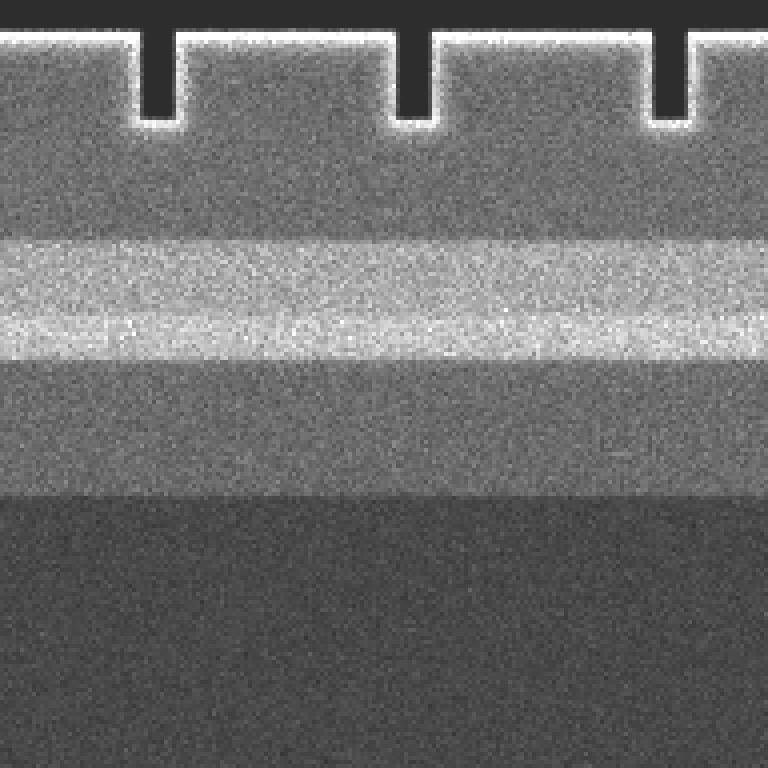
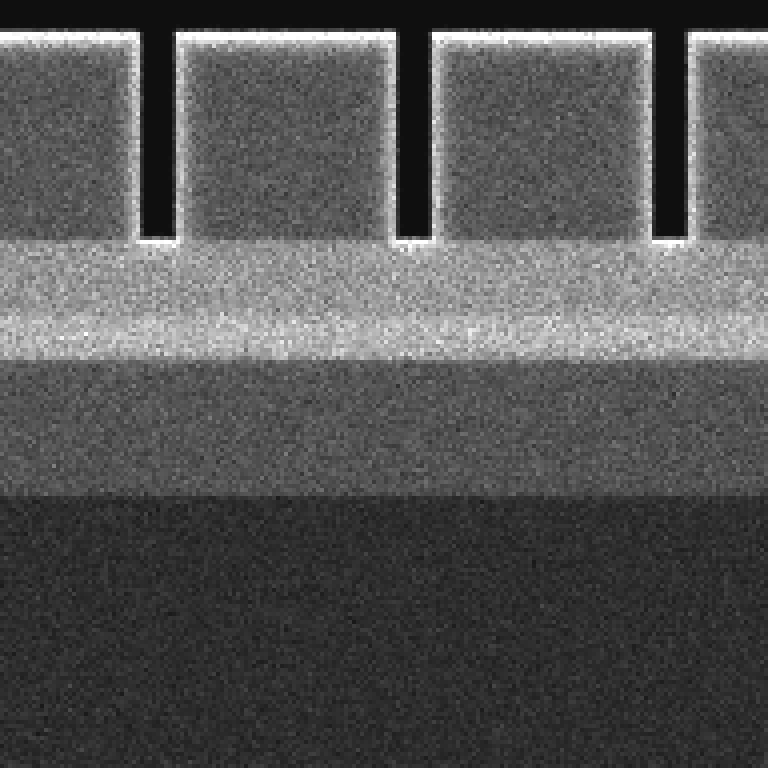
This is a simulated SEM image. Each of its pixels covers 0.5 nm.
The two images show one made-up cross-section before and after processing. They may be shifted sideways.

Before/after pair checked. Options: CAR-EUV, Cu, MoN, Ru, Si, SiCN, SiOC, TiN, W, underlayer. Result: removed underlayer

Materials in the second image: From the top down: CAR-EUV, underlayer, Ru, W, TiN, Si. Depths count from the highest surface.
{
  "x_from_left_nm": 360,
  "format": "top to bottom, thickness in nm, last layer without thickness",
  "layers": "CAR-EUV 44, underlayer 60, Ru 38, W 22, TiN 68, Si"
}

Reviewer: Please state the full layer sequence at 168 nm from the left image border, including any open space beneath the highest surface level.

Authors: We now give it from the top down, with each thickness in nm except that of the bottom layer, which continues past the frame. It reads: CAR-EUV 44, underlayer 60, Ru 38, W 22, TiN 68, Si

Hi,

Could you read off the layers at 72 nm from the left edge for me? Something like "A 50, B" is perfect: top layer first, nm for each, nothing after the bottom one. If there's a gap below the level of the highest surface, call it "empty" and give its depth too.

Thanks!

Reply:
empty 104, Ru 38, W 22, TiN 68, Si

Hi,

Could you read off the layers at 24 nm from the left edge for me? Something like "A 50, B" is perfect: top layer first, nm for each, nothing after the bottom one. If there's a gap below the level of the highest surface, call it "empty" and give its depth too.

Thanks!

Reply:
CAR-EUV 44, underlayer 60, Ru 38, W 22, TiN 68, Si